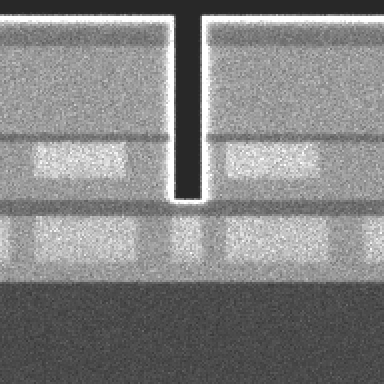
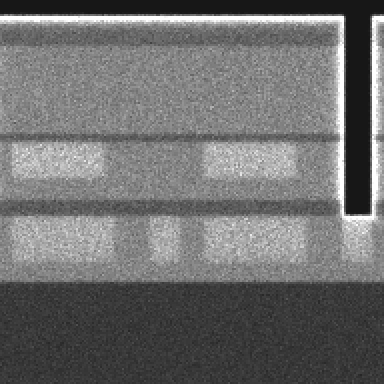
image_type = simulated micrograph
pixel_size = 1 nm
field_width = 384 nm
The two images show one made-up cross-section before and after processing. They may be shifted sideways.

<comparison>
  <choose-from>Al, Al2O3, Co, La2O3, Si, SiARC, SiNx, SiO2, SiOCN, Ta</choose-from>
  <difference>SiNx removed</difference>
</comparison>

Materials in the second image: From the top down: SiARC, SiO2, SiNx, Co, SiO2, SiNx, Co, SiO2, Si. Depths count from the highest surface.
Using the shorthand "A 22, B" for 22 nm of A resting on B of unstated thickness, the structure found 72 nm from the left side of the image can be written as SiARC 30, SiO2 88, SiNx 8, Co 36, SiO2 22, SiNx 16, Co 46, SiO2 20, Si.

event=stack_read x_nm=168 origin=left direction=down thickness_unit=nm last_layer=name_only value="SiARC 30, SiO2 88, SiNx 8, SiO2 58, SiNx 16, Co 46, SiO2 20, Si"